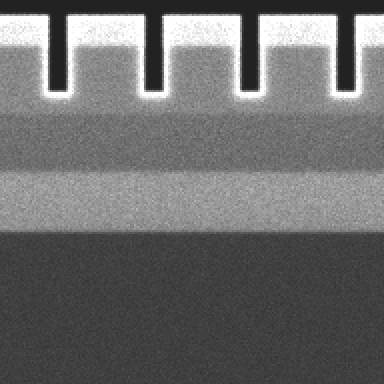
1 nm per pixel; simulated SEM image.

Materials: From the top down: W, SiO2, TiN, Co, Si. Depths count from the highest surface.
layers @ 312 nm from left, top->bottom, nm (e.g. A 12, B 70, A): W 30, SiO2 68, TiN 58, Co 60, Si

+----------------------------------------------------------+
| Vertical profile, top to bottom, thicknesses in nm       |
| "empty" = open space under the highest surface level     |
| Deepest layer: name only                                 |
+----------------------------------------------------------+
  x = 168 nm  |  W 30, SiO2 68, TiN 58, Co 60, Si